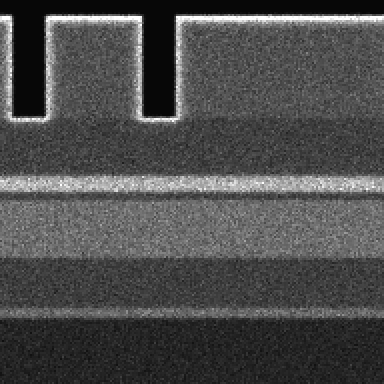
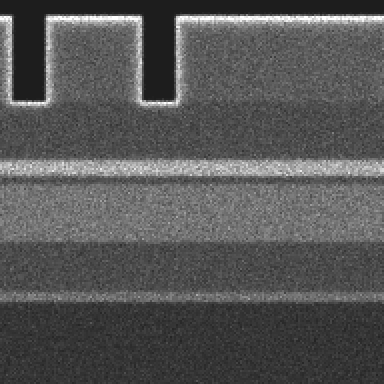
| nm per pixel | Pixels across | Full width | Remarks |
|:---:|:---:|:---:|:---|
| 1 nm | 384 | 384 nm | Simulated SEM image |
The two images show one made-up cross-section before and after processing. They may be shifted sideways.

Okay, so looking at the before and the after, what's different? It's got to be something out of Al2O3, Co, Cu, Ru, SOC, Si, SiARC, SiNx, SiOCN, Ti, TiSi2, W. SiARC, removed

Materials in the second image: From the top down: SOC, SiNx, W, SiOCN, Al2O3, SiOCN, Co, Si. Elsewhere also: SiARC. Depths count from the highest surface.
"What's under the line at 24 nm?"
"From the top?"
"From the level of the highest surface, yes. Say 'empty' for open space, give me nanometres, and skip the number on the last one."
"empty 86, SiNx 58, W 16, SiOCN 8, Al2O3 58, SiOCN 50, Co 10, Si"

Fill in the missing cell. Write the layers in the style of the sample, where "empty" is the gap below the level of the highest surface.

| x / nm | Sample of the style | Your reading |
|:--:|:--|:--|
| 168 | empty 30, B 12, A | empty 86, SiNx 58, W 16, SiOCN 8, Al2O3 58, SiOCN 50, Co 10, Si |